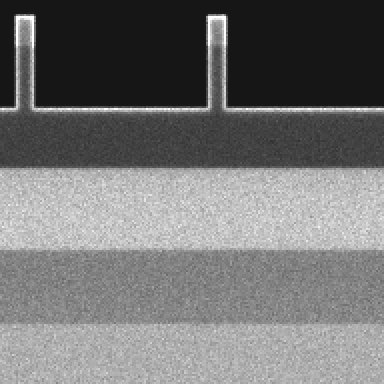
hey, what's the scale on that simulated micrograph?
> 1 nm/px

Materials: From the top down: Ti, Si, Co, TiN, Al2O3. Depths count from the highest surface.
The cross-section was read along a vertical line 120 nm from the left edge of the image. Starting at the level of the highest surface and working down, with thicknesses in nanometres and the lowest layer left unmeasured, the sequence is empty 92, Si 60, Co 82, TiN 74, Al2O3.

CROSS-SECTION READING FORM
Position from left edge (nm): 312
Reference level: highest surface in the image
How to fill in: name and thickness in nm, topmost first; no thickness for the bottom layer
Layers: empty 92, Si 60, Co 82, TiN 74, Al2O3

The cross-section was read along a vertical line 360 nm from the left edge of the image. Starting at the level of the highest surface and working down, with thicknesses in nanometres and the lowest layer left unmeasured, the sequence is empty 92, Si 60, Co 82, TiN 74, Al2O3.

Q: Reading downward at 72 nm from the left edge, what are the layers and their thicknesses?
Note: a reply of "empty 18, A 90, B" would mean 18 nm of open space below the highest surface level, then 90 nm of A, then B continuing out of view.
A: empty 92, Si 60, Co 82, TiN 74, Al2O3